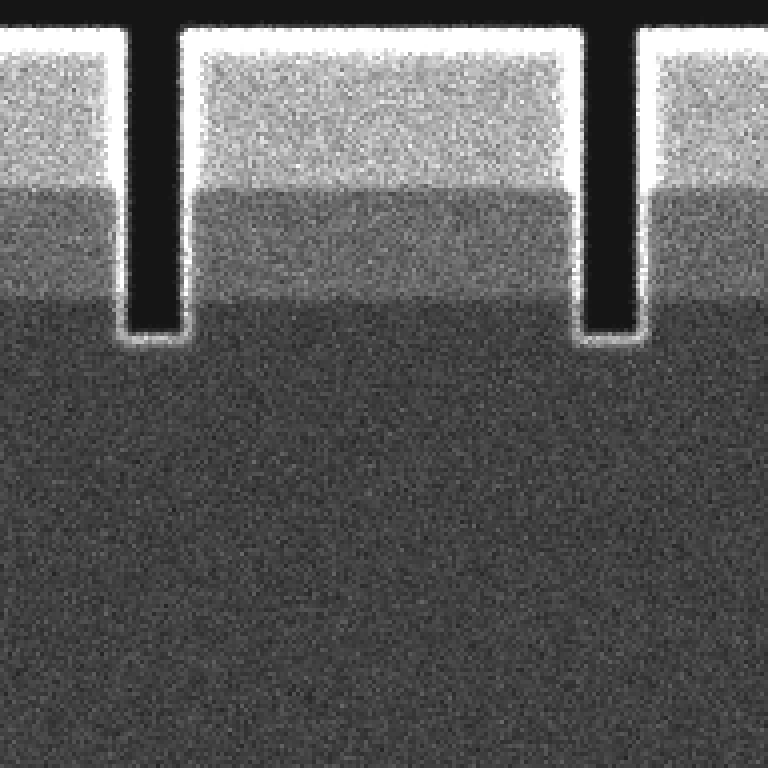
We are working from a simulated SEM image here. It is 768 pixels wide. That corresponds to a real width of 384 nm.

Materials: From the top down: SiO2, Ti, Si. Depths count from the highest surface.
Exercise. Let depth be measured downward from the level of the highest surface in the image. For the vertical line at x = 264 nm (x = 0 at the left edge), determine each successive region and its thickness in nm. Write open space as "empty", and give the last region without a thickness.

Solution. SiO2 78, Ti 56, Si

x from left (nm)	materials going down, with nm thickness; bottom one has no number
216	SiO2 78, Ti 56, Si